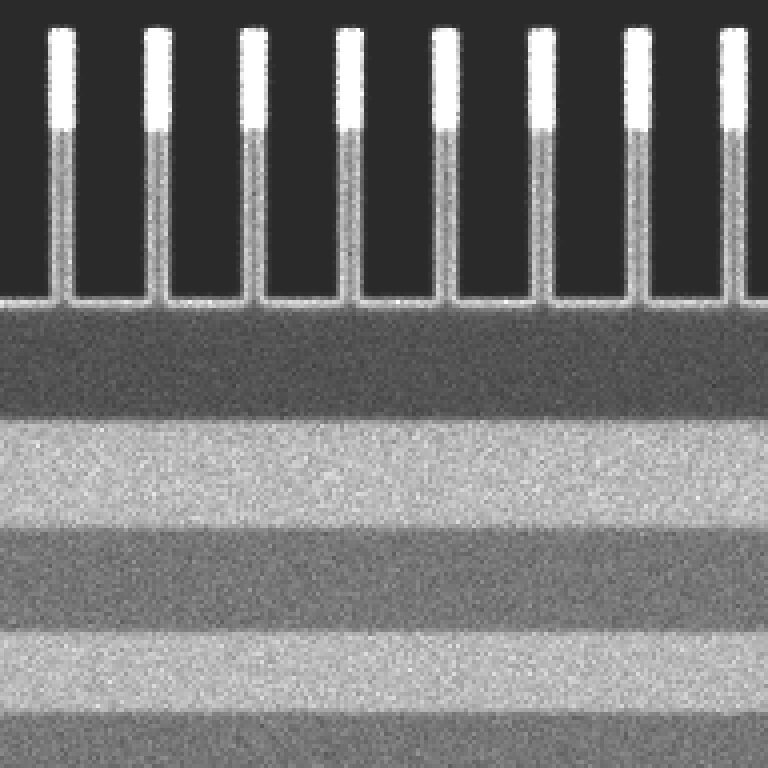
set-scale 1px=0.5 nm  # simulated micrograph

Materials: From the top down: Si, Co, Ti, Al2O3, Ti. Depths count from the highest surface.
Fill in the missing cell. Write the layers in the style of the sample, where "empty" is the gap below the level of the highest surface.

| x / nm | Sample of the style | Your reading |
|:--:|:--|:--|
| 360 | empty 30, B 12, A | empty 134, Si 60, Co 54, Ti 52, Al2O3 40, Ti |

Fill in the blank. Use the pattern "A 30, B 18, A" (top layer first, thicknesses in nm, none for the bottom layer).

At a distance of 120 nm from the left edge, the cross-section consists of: empty 134, Si 60, Co 54, Ti 52, Al2O3 40, Ti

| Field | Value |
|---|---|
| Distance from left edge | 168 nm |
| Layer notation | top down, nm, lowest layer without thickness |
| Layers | empty 134, Si 60, Co 54, Ti 52, Al2O3 40, Ti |